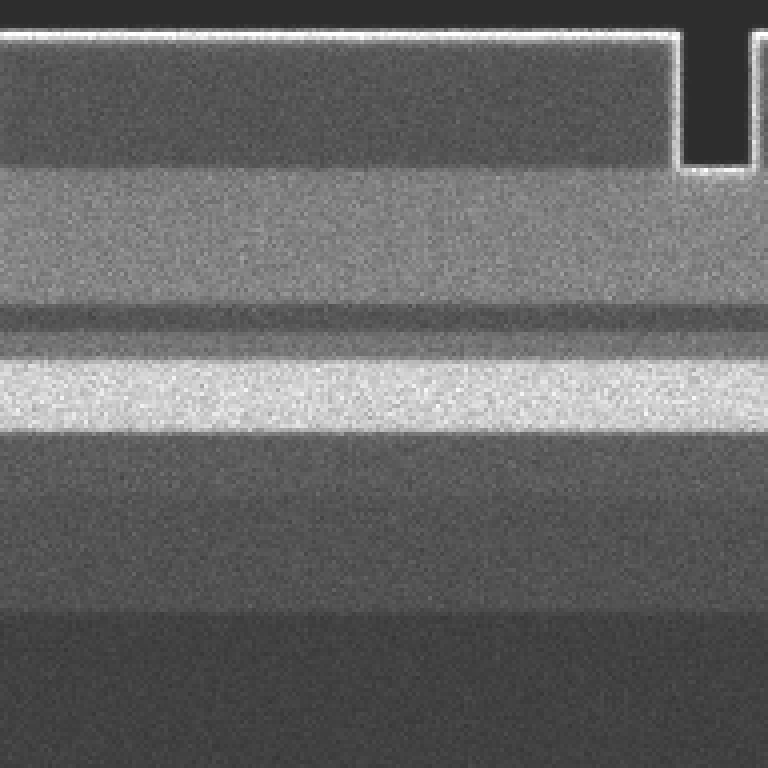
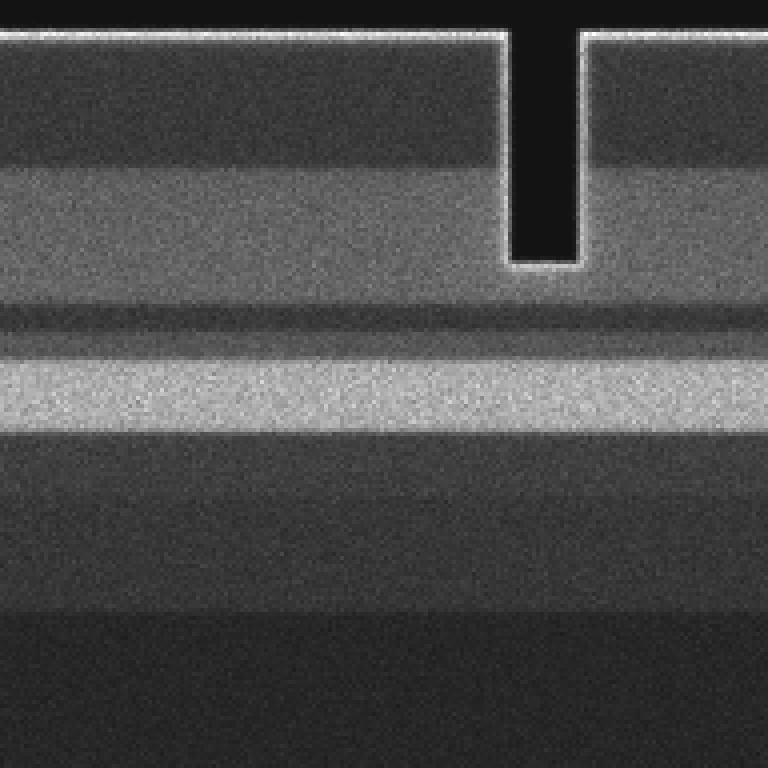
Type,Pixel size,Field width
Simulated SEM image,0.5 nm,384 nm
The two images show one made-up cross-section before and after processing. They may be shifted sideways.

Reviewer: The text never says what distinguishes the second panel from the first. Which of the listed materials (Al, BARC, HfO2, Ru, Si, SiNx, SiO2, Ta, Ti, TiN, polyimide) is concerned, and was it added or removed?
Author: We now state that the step removed Ru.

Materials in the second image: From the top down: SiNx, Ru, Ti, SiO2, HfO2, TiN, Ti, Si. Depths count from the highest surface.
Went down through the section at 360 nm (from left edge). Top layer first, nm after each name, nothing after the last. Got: SiNx 68, Ru 68, Ti 14, SiO2 14, HfO2 36, TiN 32, Ti 58, Si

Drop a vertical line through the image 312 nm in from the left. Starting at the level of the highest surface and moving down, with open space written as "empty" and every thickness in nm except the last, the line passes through SiNx 68, Ru 68, Ti 14, SiO2 14, HfO2 36, TiN 32, Ti 58, Si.